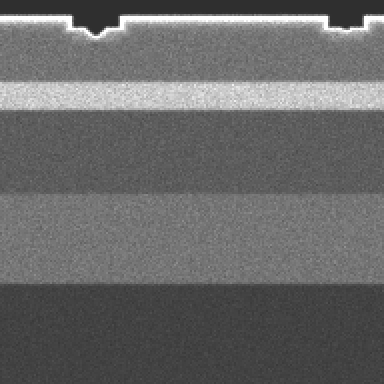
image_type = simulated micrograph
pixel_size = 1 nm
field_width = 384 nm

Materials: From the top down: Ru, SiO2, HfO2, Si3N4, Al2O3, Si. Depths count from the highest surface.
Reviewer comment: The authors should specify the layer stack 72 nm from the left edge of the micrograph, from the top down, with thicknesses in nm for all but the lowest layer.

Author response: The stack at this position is empty 12, Ru 14, SiO2 40, HfO2 28, Si3N4 84, Al2O3 90, Si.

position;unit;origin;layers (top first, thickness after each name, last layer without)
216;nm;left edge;SiO2 66, HfO2 28, Si3N4 84, Al2O3 90, Si